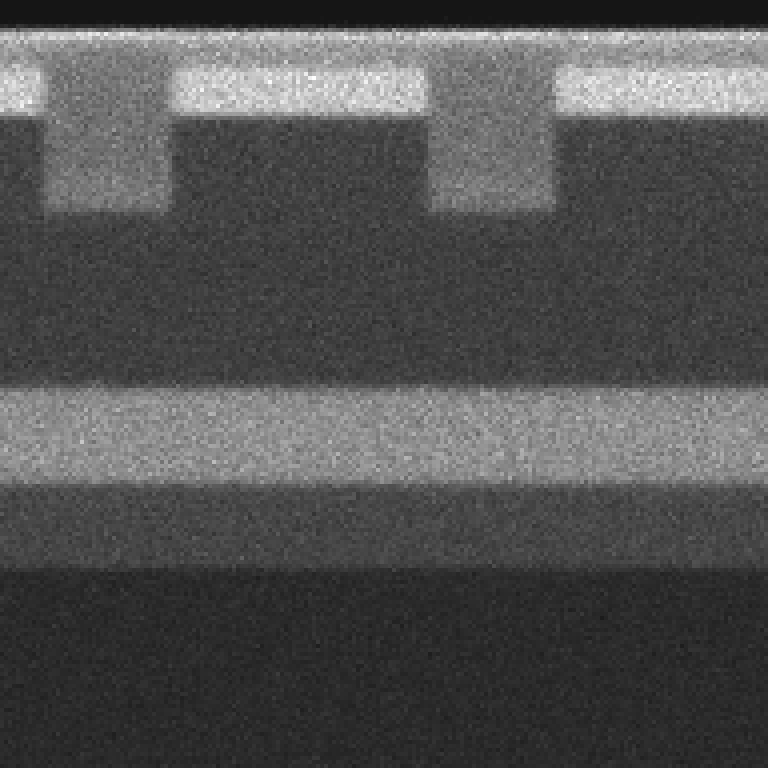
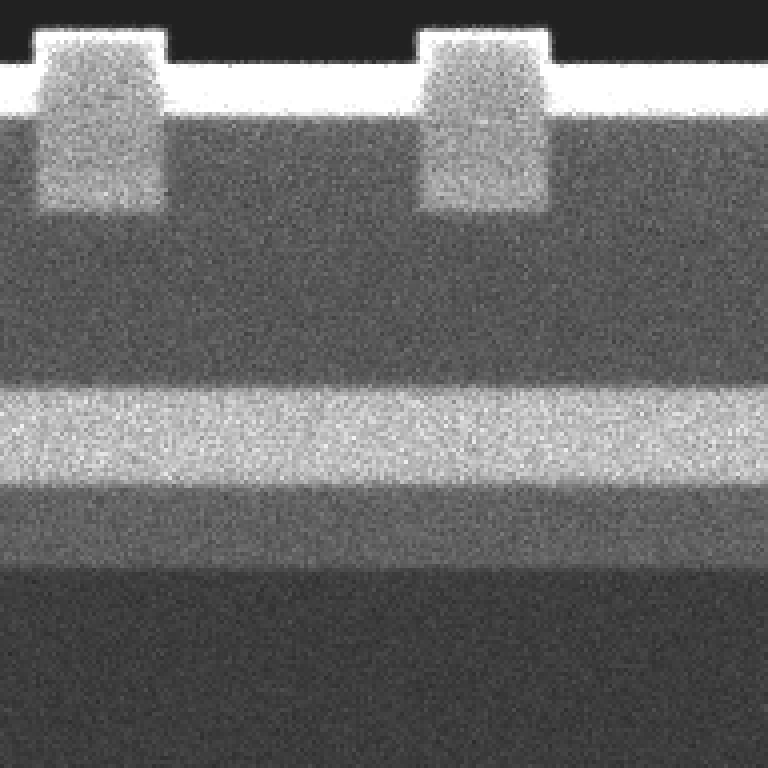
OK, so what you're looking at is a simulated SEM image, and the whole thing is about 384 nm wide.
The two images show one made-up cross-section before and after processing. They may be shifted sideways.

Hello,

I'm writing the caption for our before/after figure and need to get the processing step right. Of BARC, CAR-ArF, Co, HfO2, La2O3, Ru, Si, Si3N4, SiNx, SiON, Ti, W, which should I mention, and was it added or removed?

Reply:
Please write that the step removed Ru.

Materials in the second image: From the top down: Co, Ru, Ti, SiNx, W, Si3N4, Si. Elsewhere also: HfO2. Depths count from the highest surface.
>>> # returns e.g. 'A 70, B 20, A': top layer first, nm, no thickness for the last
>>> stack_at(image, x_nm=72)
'Co 72, Ru 18, Ti 14, SiNx 74, W 48, Si3N4 42, Si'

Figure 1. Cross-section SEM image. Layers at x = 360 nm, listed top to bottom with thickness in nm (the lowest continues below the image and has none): empty 18, HfO2 24, Ti 62, SiNx 74, W 48, Si3N4 42, Si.